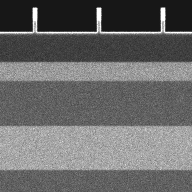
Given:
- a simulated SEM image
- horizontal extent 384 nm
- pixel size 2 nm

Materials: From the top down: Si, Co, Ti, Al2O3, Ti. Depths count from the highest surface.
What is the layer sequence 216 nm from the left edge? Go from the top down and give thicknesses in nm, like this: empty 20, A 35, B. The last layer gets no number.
empty 48, Si 60, Co 38, Ti 90, Al2O3 88, Ti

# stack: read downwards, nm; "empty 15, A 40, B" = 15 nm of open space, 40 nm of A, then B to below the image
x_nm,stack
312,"empty 48, Si 60, Co 38, Ti 90, Al2O3 88, Ti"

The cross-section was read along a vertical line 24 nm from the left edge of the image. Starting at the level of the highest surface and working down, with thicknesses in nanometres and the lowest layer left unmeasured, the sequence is empty 48, Si 60, Co 38, Ti 90, Al2O3 88, Ti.